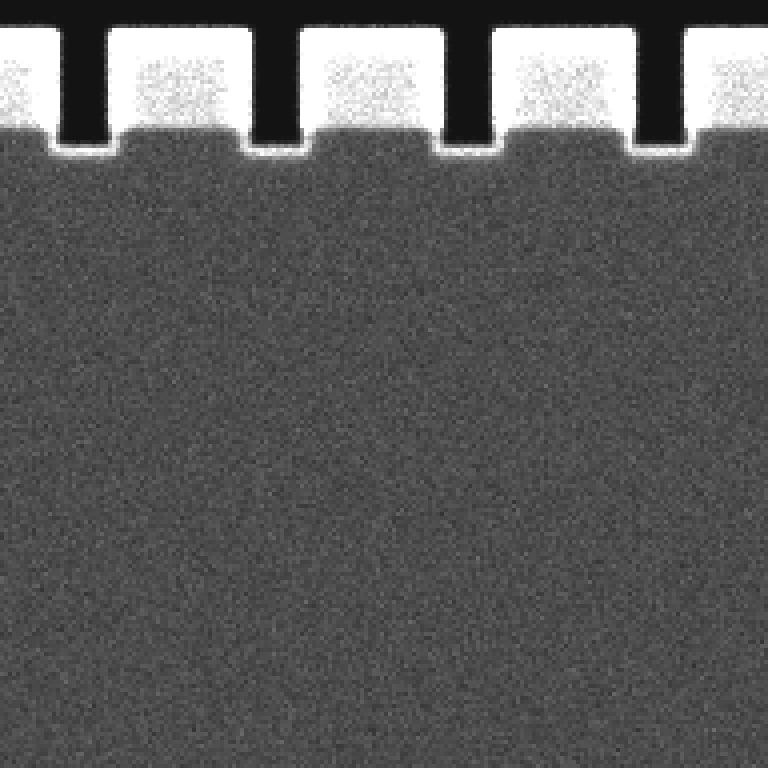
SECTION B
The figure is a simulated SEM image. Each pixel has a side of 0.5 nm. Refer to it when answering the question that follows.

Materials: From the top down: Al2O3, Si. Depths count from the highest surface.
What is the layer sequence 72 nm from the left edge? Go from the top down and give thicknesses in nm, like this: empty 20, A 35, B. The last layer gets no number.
Al2O3 48, Si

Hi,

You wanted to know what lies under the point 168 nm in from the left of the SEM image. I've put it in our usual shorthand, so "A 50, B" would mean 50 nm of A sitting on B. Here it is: Al2O3 48, Si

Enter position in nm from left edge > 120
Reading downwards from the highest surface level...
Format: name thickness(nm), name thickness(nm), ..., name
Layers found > Al2O3 48, Si